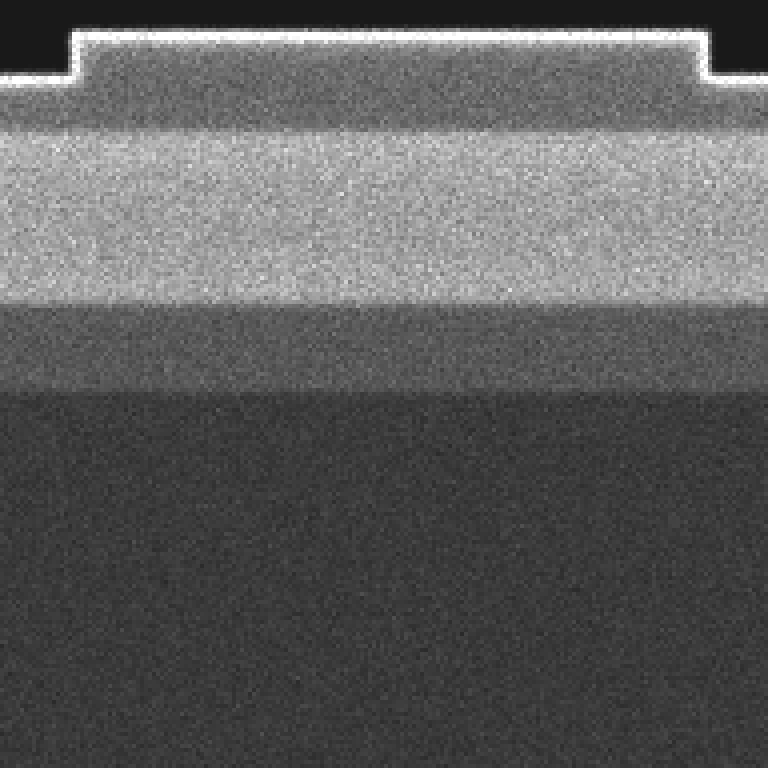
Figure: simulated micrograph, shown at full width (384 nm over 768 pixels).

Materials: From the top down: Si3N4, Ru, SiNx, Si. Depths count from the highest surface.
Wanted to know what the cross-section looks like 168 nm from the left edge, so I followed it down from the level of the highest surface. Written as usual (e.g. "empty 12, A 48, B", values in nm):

Si3N4 50, Ru 86, SiNx 44, Si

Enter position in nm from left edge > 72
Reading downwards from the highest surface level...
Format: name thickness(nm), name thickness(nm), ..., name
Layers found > Si3N4 50, Ru 86, SiNx 44, Si